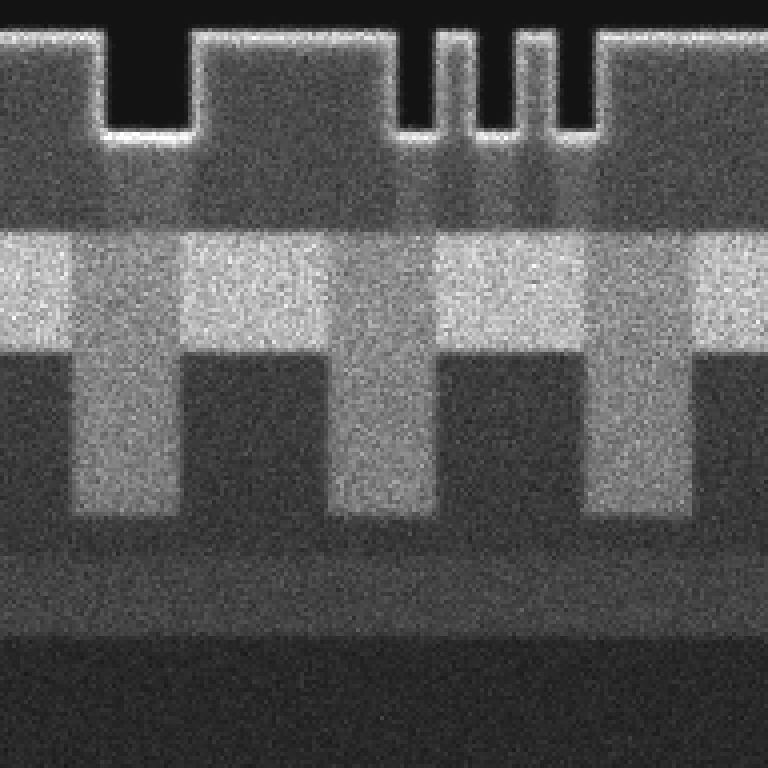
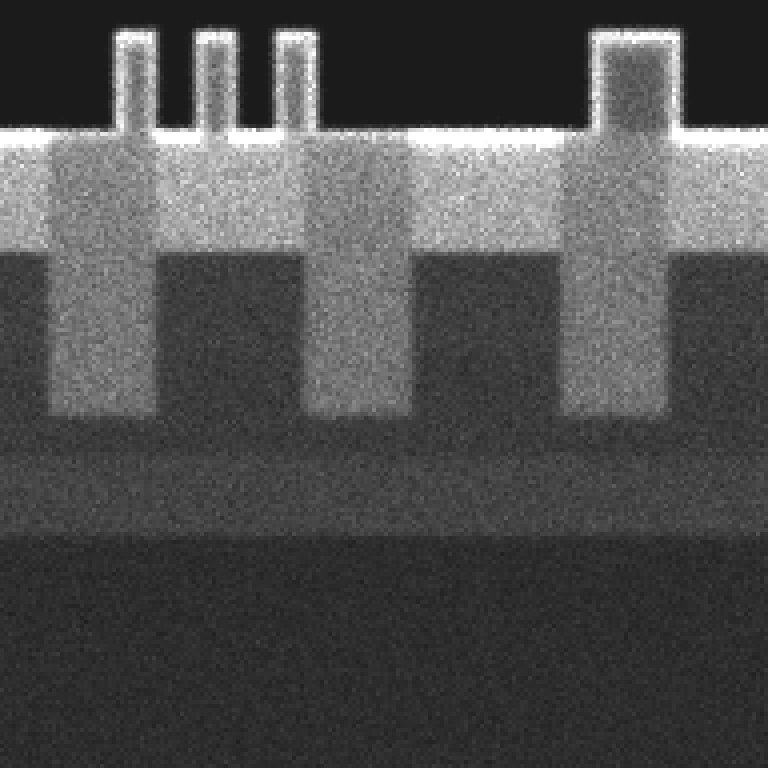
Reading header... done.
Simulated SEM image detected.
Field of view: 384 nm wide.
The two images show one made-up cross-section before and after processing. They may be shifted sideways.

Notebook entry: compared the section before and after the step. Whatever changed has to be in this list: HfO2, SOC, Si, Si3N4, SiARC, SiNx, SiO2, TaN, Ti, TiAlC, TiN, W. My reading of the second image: SOC removed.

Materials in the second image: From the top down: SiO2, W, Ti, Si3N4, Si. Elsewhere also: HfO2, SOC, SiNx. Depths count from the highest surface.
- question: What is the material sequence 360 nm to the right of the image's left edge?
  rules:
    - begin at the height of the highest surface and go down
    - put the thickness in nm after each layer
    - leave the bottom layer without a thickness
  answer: empty 50, HfO2 60, SiNx 52, Ti 50, Si3N4 40, Si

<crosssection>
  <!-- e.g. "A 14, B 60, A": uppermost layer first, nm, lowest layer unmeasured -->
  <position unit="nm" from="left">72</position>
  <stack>SiO2 50, W 142, Ti 20, Si3N4 40, Si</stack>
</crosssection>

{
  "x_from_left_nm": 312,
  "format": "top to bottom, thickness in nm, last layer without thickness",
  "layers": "SiO2 50, W 142, Ti 20, Si3N4 40, Si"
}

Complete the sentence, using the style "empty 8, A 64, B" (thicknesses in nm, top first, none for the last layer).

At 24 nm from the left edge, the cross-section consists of empty 50, W 142, Ti 20, Si3N4 40, Si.